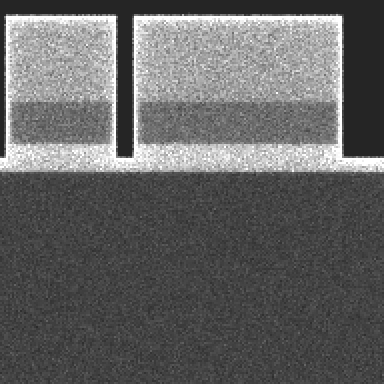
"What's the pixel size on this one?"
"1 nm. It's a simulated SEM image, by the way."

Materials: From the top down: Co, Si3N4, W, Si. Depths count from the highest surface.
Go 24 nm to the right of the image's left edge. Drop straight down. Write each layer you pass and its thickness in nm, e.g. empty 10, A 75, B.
Co 86, Si3N4 42, W 28, Si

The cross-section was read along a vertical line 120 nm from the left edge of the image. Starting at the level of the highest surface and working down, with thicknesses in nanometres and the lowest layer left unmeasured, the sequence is empty 142, W 14, Si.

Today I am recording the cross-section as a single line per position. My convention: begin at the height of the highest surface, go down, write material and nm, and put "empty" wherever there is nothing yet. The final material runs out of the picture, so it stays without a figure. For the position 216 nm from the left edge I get Co 86, Si3N4 42, W 28, Si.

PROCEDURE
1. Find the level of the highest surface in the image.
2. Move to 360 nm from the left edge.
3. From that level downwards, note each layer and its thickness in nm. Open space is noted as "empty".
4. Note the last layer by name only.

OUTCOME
empty 142, W 14, Si